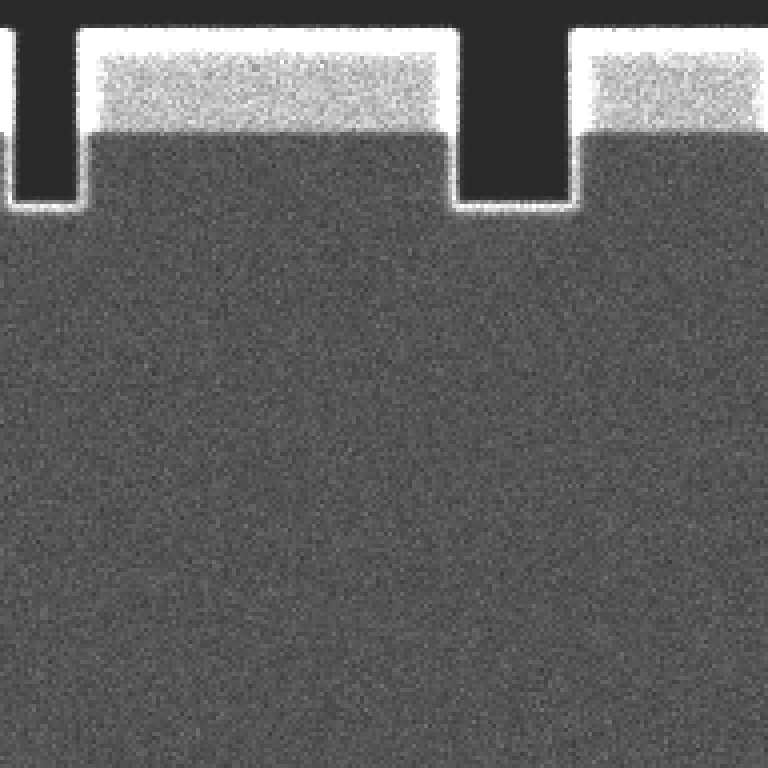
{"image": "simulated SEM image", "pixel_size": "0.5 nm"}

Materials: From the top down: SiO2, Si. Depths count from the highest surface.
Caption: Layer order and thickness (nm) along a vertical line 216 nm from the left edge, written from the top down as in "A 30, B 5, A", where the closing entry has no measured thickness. SiO2 50, Si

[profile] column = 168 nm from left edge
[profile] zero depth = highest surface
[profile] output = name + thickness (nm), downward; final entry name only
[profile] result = SiO2 50, Si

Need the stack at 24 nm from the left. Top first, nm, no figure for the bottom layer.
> empty 86, Si